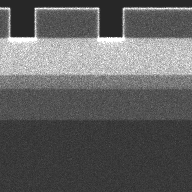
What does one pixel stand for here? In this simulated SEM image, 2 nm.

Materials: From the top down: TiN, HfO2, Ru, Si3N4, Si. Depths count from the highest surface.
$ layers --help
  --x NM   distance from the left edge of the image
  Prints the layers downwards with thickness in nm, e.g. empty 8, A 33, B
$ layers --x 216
empty 60, HfO2 74, Ru 28, Si3N4 62, Si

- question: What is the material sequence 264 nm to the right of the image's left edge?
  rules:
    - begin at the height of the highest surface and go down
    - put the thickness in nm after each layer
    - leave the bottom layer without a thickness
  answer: TiN 60, HfO2 74, Ru 28, Si3N4 62, Si